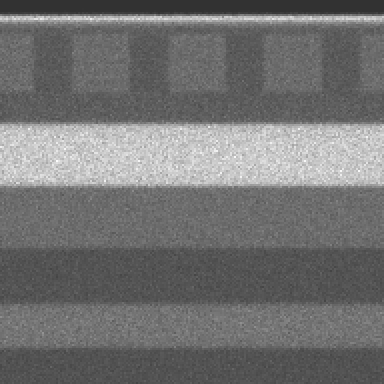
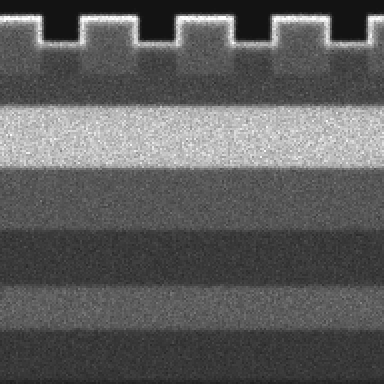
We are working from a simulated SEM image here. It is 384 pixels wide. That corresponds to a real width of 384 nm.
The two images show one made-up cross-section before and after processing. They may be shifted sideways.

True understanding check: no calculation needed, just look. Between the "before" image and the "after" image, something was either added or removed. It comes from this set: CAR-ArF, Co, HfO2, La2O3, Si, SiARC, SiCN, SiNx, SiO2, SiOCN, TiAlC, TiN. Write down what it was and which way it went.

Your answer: SiARC (removed)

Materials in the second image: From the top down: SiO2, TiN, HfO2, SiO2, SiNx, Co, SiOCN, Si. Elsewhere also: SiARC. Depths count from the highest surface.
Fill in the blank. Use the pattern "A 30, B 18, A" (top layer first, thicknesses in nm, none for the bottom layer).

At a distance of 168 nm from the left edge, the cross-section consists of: empty 26, SiARC 32, TiN 32, HfO2 62, SiO2 62, SiNx 56, Co 44, SiOCN 50, Si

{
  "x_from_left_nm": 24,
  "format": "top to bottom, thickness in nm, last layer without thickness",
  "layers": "SiO2 58, TiN 32, HfO2 62, SiO2 62, SiNx 56, Co 44, SiOCN 50, Si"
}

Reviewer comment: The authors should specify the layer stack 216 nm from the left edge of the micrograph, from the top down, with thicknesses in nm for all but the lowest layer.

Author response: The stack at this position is SiO2 58, TiN 32, HfO2 62, SiO2 62, SiNx 56, Co 44, SiOCN 50, Si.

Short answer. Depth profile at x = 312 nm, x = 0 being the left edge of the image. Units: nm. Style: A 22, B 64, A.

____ SiO2 58, TiN 32, HfO2 62, SiO2 62, SiNx 56, Co 44, SiOCN 50, Si